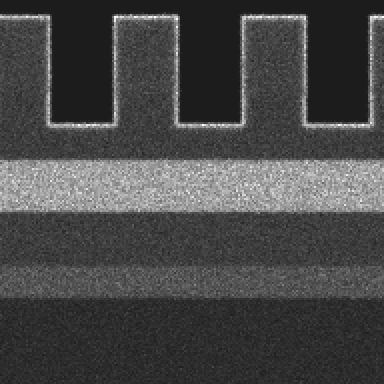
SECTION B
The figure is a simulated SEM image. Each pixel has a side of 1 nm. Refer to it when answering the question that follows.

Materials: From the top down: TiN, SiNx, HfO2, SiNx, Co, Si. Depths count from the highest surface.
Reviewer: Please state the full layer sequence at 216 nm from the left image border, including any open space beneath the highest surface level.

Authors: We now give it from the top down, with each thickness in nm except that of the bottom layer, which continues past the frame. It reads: empty 108, SiNx 36, HfO2 52, SiNx 54, Co 32, Si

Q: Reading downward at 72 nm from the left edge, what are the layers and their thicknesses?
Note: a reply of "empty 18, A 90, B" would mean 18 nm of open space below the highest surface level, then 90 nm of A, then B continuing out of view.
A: empty 108, SiNx 36, HfO2 52, SiNx 54, Co 32, Si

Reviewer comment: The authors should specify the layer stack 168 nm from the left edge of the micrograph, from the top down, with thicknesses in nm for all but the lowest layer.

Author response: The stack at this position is TiN 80, SiNx 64, HfO2 52, SiNx 54, Co 32, Si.